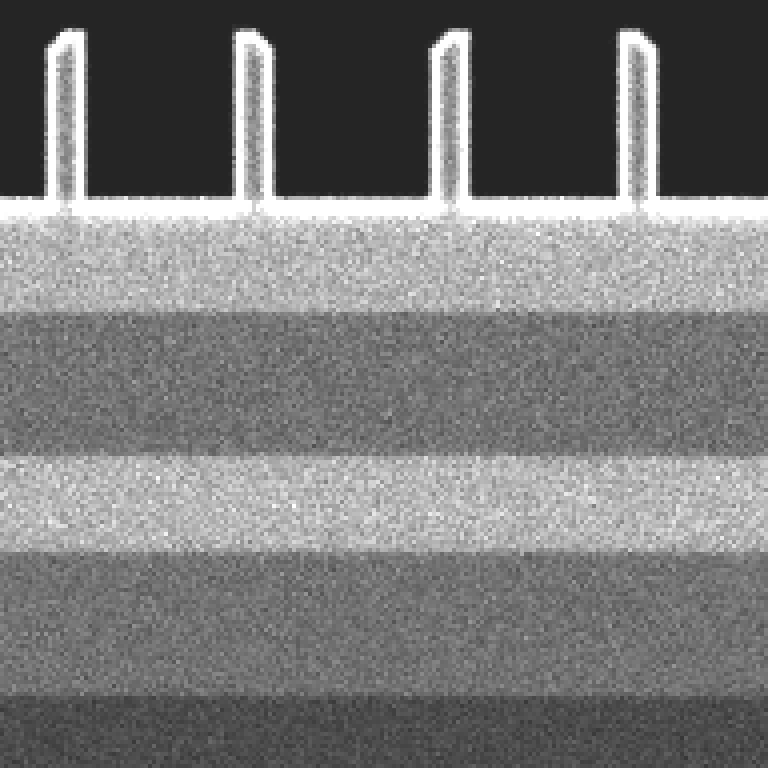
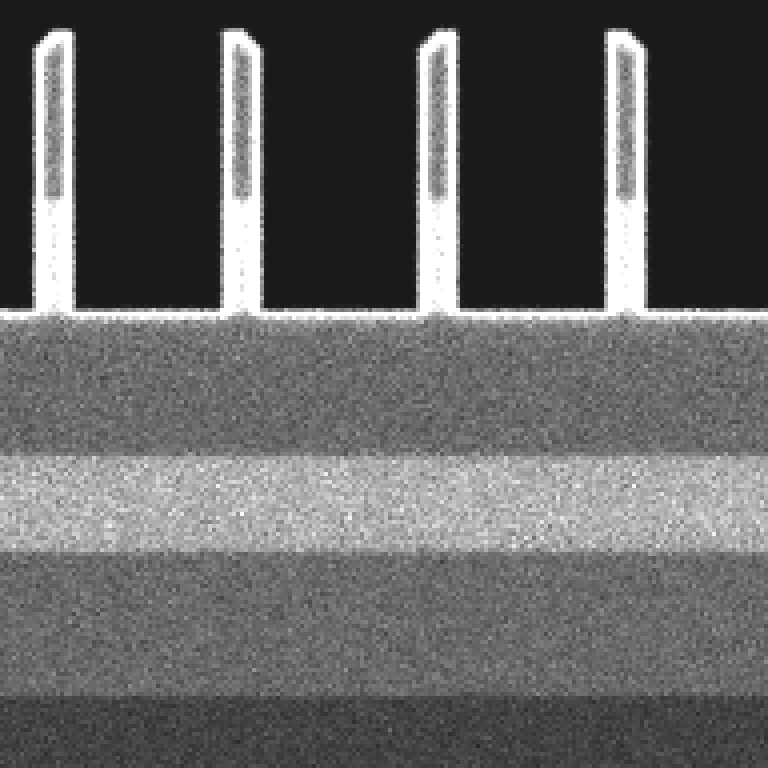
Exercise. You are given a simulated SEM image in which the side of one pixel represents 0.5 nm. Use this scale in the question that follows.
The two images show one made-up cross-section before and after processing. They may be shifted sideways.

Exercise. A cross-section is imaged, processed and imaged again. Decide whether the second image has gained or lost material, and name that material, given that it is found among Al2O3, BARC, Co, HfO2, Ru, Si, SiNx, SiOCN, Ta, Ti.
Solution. removed: Al2O3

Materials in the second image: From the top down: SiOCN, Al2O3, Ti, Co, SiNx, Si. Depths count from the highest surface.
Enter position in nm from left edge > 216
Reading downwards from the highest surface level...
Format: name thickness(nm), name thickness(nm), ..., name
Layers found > empty 2, SiOCN 82, Al2O3 56, Ti 72, Co 48, SiNx 72, Si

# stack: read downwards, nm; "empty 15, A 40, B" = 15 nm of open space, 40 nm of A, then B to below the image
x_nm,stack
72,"empty 140, Ti 72, Co 48, SiNx 72, Si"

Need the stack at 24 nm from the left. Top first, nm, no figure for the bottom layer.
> empty 2, SiOCN 82, Al2O3 56, Ti 72, Co 48, SiNx 72, Si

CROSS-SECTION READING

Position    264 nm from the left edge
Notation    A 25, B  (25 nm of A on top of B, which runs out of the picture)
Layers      empty 140, Ti 72, Co 48, SiNx 72, Si